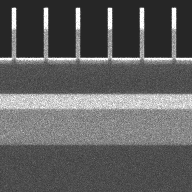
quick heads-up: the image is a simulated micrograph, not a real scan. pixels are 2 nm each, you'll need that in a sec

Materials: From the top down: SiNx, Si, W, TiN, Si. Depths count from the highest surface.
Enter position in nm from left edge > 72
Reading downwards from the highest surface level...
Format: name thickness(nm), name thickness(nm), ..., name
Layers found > empty 100, SiNx 12, Si 60, W 30, TiN 72, Si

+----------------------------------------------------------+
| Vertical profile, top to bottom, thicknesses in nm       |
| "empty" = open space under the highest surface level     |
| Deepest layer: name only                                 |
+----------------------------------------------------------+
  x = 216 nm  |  Si 172, W 30, TiN 72, Si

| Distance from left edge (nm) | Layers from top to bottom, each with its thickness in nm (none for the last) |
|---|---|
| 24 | Si 172, W 30, TiN 72, Si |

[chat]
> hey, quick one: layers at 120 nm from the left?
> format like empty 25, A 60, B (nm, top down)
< empty 100, SiNx 12, Si 60, W 30, TiN 72, Si